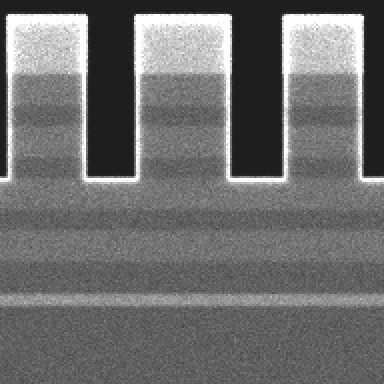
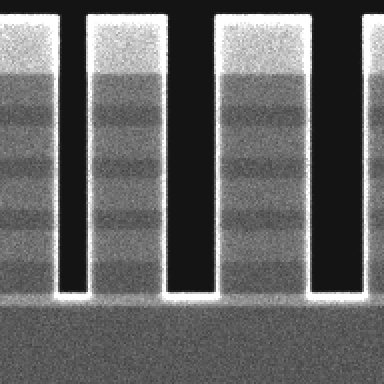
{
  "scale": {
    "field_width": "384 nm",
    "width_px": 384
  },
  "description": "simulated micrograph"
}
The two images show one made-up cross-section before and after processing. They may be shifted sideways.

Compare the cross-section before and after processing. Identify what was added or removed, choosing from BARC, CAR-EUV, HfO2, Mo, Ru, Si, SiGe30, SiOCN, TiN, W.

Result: Si and SiGe30 removed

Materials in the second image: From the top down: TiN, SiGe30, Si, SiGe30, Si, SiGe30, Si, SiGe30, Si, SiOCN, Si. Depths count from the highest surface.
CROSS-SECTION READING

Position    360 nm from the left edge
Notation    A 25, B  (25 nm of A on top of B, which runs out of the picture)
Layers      empty 278, SiOCN 12, Si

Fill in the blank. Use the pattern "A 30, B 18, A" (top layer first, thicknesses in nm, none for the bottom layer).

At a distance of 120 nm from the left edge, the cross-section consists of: TiN 58, SiGe30 32, Si 20, SiGe30 32, Si 20, SiGe30 32, Si 20, SiGe30 32, Si 32, SiOCN 12, Si